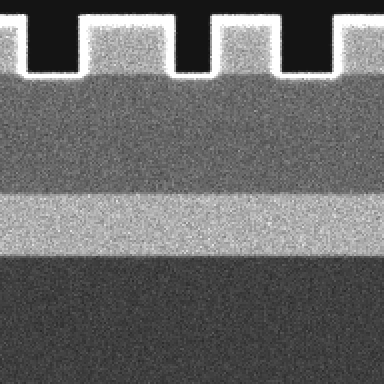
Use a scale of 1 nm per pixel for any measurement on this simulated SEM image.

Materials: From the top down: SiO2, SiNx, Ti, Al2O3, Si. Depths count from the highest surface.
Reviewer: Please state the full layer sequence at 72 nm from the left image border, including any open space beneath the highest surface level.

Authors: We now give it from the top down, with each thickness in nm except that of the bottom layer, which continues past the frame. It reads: empty 58, SiNx 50, Ti 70, Al2O3 62, Si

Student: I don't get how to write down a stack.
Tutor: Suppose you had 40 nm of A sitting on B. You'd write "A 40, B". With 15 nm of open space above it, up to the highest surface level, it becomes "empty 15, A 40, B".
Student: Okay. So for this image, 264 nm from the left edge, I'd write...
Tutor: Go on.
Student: SiO2 58, SiNx 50, Ti 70, Al2O3 62, Si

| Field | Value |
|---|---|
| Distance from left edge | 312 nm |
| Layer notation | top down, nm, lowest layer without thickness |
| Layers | empty 58, SiNx 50, Ti 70, Al2O3 62, Si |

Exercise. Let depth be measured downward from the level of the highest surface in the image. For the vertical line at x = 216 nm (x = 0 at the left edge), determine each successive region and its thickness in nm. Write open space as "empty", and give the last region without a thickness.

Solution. SiO2 58, SiNx 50, Ti 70, Al2O3 62, Si